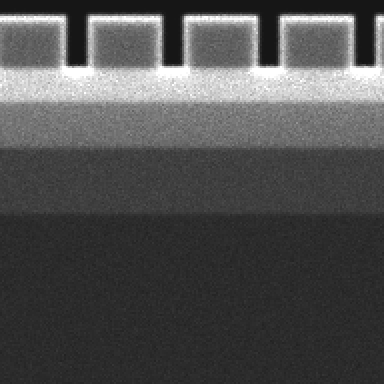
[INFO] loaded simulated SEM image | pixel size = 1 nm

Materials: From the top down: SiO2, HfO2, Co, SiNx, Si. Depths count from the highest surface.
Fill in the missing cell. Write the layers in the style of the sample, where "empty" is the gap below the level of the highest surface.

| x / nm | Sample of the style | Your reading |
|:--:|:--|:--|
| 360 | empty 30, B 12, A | empty 52, HfO2 34, Co 46, SiNx 66, Si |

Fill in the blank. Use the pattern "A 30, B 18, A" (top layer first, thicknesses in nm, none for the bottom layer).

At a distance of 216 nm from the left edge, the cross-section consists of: SiO2 52, HfO2 34, Co 46, SiNx 66, Si